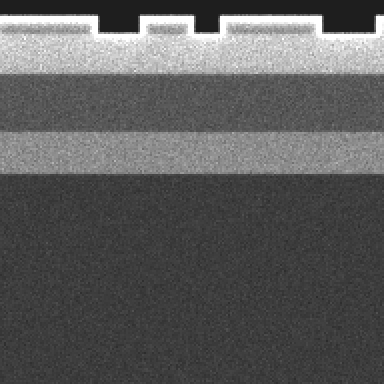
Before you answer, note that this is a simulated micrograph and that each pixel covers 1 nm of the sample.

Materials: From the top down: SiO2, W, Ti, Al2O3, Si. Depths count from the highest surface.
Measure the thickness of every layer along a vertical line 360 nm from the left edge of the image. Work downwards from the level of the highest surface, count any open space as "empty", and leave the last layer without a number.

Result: empty 18, W 40, Ti 58, Al2O3 42, Si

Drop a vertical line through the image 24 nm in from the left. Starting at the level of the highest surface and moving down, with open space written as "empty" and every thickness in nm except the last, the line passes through SiO2 18, W 40, Ti 58, Al2O3 42, Si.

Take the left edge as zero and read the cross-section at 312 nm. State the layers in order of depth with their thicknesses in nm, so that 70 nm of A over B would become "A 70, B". SiO2 18, W 40, Ti 58, Al2O3 42, Si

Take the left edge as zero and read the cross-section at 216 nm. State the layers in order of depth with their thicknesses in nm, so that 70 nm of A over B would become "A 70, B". empty 18, W 40, Ti 58, Al2O3 42, Si